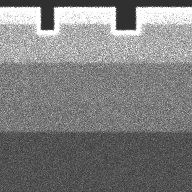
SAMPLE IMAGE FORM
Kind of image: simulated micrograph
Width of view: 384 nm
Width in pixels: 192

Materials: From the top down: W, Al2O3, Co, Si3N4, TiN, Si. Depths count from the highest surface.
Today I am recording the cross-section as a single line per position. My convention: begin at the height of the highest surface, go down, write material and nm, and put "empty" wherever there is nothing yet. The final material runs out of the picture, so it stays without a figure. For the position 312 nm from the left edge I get W 32, Al2O3 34, Co 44, Si3N4 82, TiN 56, Si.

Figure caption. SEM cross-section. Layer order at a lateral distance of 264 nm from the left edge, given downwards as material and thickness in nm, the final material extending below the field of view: empty 46, Al2O3 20, Co 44, Si3N4 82, TiN 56, Si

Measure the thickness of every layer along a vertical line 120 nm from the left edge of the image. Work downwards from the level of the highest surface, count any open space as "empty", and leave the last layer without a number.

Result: W 32, Al2O3 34, Co 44, Si3N4 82, TiN 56, Si